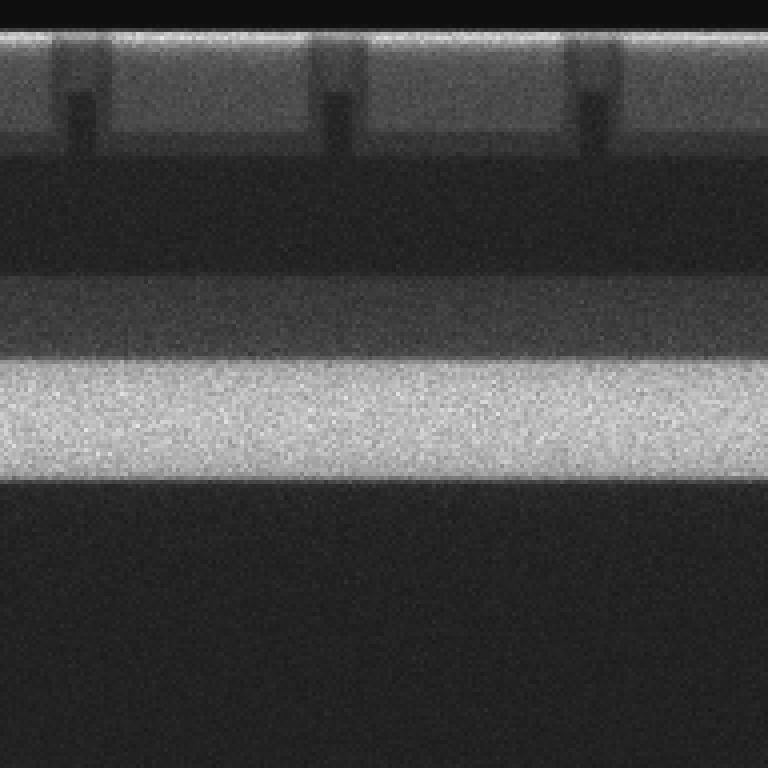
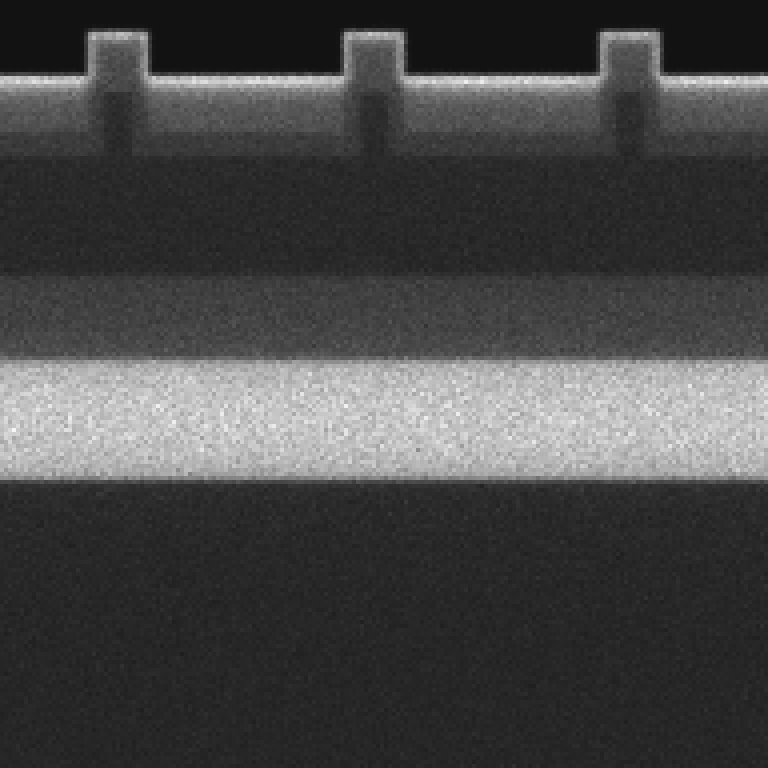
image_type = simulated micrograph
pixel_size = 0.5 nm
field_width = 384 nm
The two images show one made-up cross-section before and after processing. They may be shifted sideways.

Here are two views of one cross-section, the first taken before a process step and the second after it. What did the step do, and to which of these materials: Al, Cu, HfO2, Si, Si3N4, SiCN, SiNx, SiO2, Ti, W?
It removed SiO2.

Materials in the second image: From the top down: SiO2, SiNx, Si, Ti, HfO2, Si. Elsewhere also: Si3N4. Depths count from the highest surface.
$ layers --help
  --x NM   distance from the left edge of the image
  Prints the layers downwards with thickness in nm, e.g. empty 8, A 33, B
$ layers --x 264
empty 22, SiO2 28, SiNx 12, Si 60, Ti 42, HfO2 60, Si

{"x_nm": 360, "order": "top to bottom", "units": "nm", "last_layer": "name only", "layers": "empty 22, SiO2 28, SiNx 12, Si 60, Ti 42, HfO2 60, Si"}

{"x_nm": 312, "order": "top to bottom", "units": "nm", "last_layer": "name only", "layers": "Si3N4 30, Si 92, Ti 42, HfO2 60, Si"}